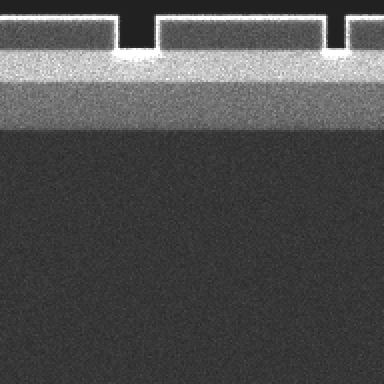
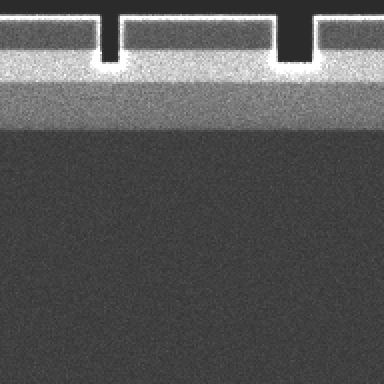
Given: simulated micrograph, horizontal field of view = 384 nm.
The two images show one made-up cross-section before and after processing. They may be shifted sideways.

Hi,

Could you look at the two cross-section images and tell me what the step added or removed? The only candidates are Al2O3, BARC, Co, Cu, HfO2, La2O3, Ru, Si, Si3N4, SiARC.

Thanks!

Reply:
removed HfO2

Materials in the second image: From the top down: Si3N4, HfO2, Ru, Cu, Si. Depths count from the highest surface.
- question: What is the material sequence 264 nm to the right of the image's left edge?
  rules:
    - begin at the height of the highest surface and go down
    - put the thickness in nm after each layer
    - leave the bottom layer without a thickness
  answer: Si3N4 34, HfO2 32, Ru 40, Cu 8, Si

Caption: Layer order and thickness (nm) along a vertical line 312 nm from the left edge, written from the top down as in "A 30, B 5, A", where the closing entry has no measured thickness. empty 48, HfO2 18, Ru 40, Cu 8, Si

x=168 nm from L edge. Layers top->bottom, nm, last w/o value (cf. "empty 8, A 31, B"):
Si3N4 34, HfO2 32, Ru 40, Cu 8, Si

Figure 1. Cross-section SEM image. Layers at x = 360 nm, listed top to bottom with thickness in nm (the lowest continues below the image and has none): Si3N4 34, HfO2 32, Ru 40, Cu 8, Si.